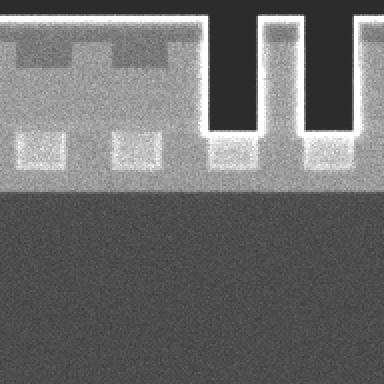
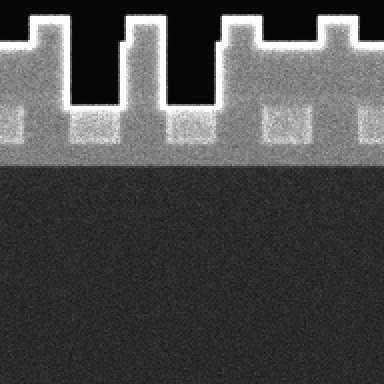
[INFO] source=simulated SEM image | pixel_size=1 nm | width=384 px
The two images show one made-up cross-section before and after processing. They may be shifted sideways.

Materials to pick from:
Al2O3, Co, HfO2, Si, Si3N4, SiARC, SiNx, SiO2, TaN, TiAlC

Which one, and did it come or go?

SiARC - removed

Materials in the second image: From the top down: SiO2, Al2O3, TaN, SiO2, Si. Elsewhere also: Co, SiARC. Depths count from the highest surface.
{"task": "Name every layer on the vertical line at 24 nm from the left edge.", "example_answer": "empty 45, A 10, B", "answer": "empty 26, SiO2 52, Al2O3 12, SiO2 60, Si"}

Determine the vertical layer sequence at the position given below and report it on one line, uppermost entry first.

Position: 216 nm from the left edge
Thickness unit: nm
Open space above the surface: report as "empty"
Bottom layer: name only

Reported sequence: empty 26, SiO2 52, Al2O3 12, SiO2 60, Si